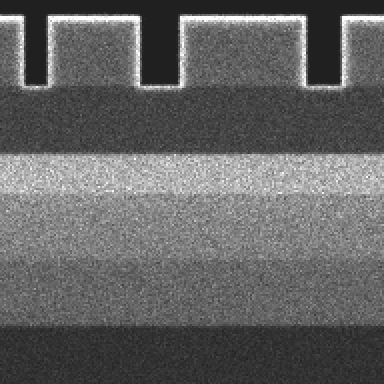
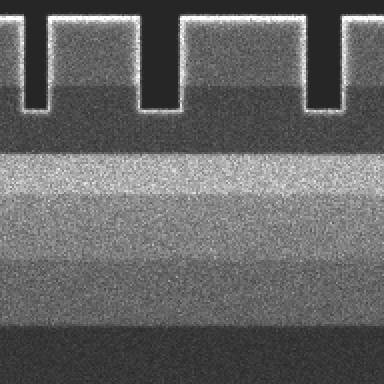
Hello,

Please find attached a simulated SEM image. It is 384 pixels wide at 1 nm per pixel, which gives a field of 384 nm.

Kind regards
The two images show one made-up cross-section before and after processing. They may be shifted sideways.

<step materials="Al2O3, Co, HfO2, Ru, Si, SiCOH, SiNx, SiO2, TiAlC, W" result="removed SiNx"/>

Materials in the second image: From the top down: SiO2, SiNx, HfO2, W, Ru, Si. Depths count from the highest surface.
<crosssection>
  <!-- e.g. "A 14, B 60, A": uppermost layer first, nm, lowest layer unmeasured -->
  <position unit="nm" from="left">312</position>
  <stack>empty 94, SiNx 44, HfO2 40, W 66, Ru 66, Si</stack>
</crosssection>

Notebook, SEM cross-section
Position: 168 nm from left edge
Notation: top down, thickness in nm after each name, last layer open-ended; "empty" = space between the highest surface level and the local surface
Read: empty 94, SiNx 44, HfO2 40, W 66, Ru 66, Si